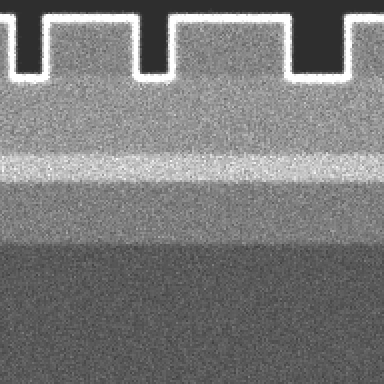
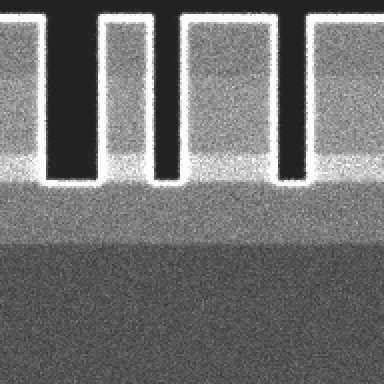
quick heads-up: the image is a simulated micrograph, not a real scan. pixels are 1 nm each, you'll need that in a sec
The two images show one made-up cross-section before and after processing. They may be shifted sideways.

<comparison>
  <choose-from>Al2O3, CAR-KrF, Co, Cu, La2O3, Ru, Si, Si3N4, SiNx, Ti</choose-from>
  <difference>Co and Si3N4 removed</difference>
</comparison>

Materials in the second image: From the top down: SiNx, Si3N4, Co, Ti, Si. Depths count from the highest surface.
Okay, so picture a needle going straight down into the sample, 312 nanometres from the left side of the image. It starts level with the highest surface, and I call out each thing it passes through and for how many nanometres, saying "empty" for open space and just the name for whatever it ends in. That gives SiNx 60, Si3N4 78, Co 28, Ti 62, Si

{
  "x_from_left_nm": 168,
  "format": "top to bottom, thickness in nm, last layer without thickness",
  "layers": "empty 166, Ti 62, Si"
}